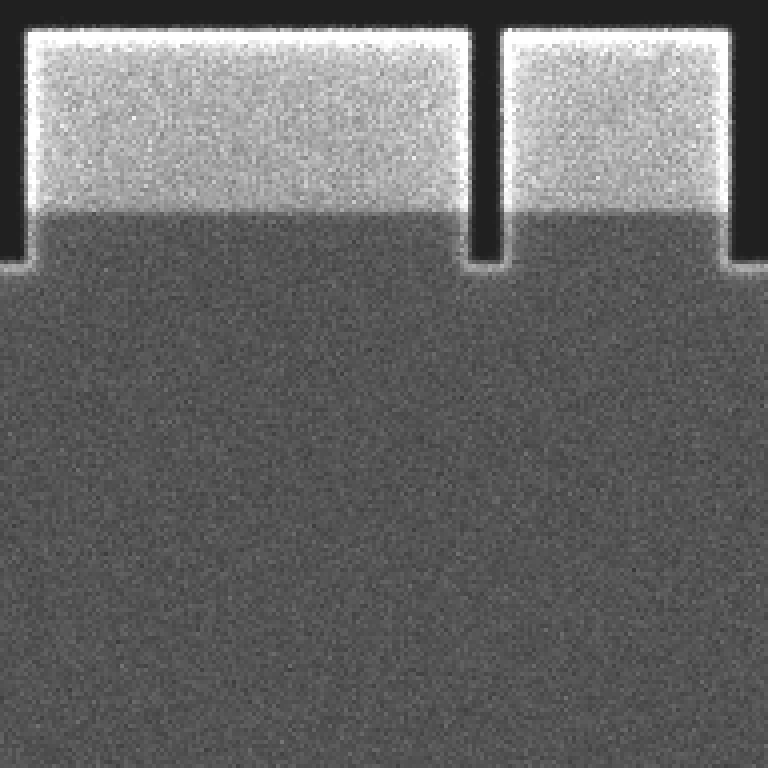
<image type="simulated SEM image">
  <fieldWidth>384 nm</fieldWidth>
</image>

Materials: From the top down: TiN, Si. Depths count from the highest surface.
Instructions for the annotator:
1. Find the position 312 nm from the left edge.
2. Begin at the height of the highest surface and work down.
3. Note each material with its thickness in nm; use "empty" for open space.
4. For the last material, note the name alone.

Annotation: TiN 90, Si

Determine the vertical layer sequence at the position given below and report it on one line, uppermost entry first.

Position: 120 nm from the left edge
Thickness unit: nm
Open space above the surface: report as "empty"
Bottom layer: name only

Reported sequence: TiN 90, Si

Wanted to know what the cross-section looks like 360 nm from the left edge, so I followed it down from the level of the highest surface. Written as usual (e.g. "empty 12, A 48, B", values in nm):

TiN 90, Si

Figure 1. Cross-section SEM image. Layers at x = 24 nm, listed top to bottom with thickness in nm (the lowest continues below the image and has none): TiN 90, Si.